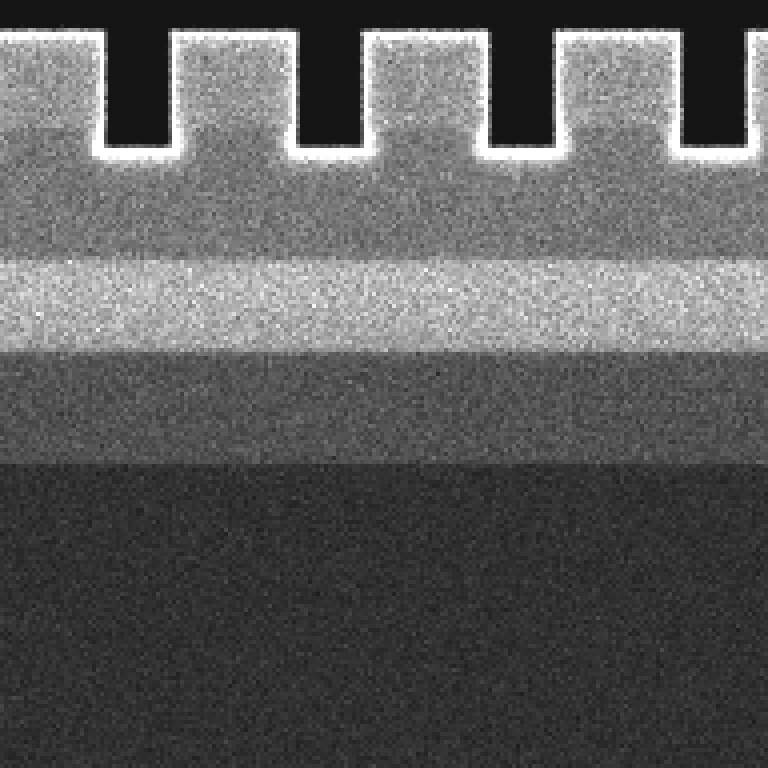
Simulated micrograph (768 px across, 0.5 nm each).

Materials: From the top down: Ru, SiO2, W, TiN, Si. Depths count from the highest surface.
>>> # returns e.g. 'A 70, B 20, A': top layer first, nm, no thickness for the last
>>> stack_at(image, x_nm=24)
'Ru 48, SiO2 66, W 46, TiN 56, Si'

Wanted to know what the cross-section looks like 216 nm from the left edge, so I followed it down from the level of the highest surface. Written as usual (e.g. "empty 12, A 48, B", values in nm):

Ru 48, SiO2 66, W 46, TiN 56, Si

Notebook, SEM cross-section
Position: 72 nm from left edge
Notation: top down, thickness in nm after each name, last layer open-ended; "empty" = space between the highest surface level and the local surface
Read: empty 58, SiO2 56, W 46, TiN 56, Si